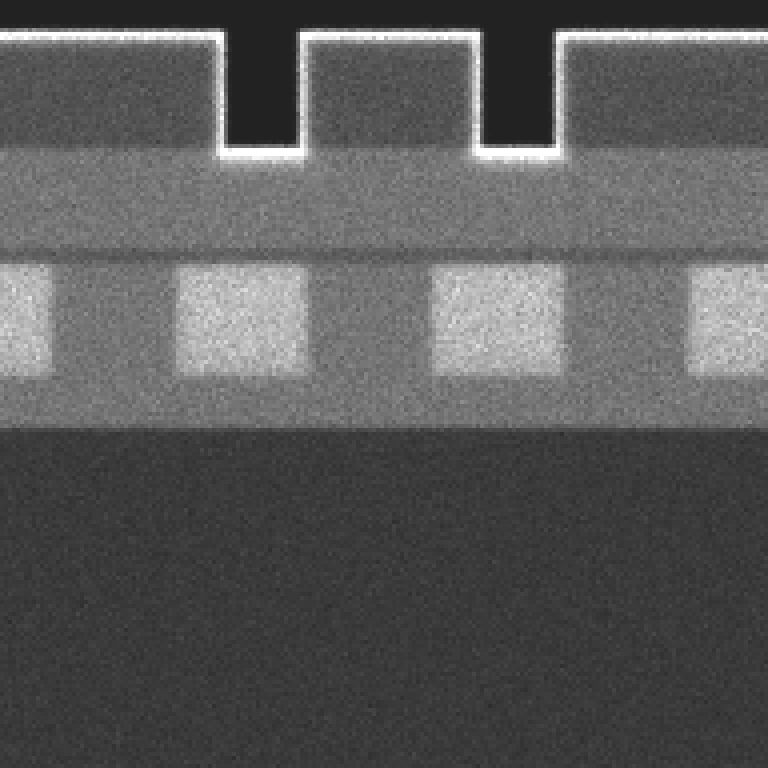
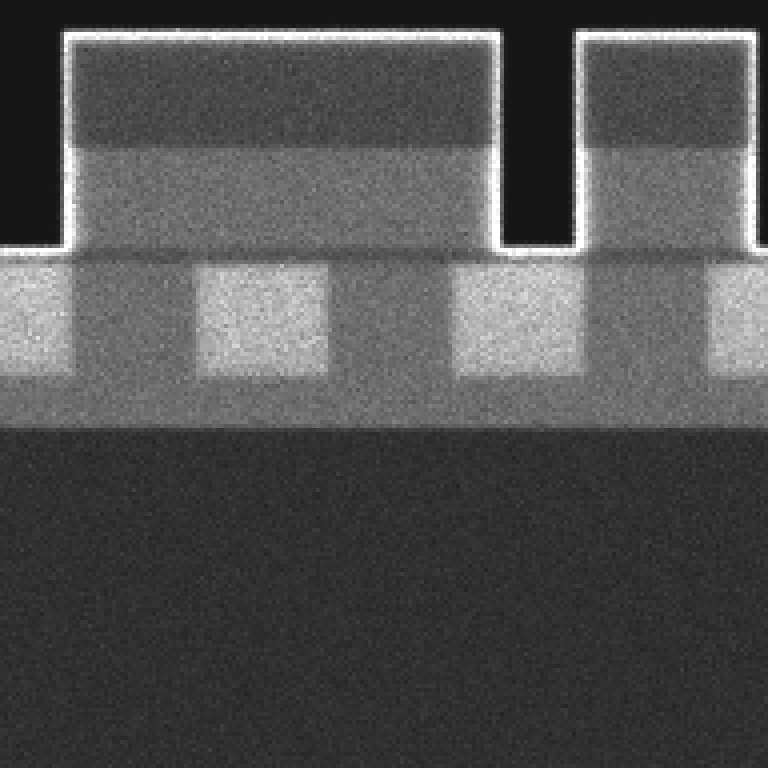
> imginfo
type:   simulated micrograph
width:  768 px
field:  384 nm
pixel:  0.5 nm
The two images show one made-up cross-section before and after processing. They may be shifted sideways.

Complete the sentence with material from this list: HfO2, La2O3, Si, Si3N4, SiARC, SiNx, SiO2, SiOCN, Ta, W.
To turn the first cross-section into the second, SiO2 must be removed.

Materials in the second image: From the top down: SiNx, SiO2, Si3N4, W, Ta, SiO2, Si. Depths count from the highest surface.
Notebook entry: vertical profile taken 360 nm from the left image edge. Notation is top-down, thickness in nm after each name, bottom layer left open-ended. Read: SiNx 58, SiO2 50, Si3N4 8, W 50, Ta 6, SiO2 26, Si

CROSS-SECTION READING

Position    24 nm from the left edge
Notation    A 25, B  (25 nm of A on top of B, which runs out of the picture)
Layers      empty 108, Si3N4 8, W 50, Ta 6, SiO2 26, Si